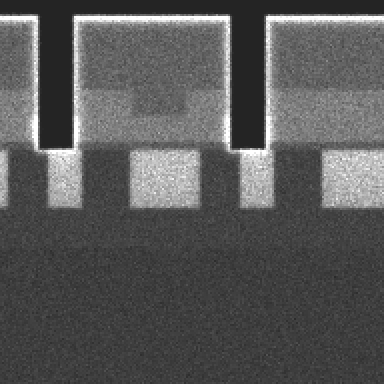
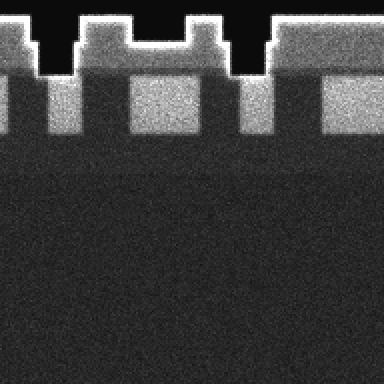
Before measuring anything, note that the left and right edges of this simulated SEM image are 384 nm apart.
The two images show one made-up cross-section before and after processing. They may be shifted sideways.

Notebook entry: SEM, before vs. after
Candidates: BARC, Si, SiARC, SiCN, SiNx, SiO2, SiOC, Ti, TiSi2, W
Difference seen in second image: SiARC removed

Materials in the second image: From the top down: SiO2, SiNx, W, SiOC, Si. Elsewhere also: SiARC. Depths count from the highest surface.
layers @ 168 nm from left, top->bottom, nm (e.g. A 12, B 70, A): empty 26, SiO2 26, SiNx 8, W 58, SiOC 40, Si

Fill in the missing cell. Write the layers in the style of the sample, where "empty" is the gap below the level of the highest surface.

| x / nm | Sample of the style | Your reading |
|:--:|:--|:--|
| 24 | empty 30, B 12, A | SiO2 52, SiNx 8, SiOC 98, Si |